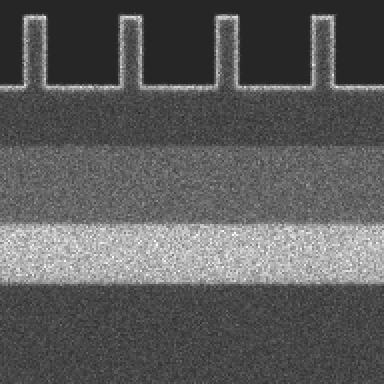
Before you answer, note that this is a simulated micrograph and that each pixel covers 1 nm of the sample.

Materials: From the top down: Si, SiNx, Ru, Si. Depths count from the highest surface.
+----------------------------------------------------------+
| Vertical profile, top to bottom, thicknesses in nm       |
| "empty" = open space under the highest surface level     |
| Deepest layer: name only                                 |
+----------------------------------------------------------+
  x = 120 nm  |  Si 130, SiNx 78, Ru 60, Si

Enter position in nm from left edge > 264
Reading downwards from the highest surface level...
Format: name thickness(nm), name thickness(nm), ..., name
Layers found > empty 70, Si 60, SiNx 78, Ru 60, Si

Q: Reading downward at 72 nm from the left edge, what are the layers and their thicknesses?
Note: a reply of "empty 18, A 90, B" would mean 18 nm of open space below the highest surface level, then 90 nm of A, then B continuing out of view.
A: empty 70, Si 60, SiNx 78, Ru 60, Si